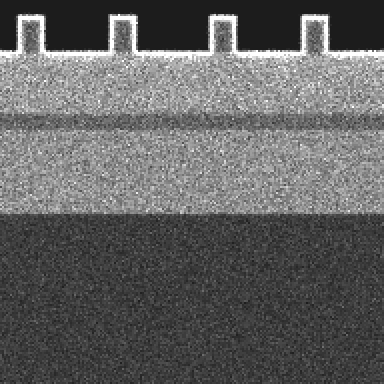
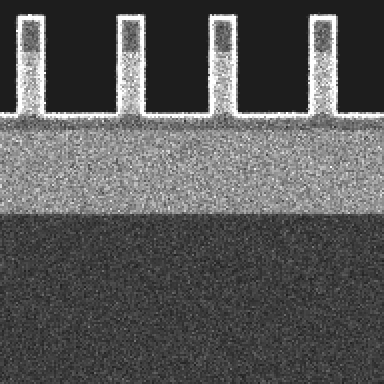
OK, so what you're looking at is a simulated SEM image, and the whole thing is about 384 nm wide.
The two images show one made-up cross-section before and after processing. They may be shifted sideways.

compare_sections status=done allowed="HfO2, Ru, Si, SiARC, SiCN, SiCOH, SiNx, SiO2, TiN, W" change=removed material="Ru"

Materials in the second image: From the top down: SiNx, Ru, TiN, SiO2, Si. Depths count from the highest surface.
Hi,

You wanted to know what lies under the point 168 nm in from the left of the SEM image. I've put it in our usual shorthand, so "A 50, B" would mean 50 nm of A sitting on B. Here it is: empty 98, TiN 16, SiO2 84, Si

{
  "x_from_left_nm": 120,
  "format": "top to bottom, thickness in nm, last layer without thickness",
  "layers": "SiNx 36, Ru 62, TiN 16, SiO2 84, Si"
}